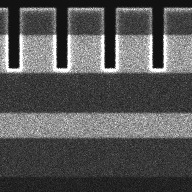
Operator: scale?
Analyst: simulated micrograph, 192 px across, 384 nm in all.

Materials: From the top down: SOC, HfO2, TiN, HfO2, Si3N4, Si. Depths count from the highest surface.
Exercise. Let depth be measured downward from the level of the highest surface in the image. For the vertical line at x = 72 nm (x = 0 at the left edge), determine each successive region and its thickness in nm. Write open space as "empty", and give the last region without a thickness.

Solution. SOC 54, HfO2 76, TiN 80, HfO2 50, Si3N4 78, Si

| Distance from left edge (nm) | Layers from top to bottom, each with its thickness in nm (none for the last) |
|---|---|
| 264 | SOC 54, HfO2 76, TiN 80, HfO2 50, Si3N4 78, Si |